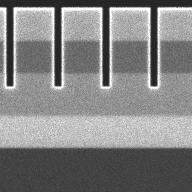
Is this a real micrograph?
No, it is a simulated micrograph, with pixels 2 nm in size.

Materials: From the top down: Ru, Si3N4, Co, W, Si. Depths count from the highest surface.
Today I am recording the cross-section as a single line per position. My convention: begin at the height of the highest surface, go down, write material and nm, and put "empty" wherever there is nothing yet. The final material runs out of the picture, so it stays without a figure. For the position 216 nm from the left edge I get empty 158, Co 58, W 64, Si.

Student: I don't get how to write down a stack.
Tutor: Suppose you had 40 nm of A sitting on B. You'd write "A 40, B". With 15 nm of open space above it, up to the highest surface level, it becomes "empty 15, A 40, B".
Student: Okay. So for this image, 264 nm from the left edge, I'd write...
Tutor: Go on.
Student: Ru 66, Si3N4 64, Co 86, W 64, Si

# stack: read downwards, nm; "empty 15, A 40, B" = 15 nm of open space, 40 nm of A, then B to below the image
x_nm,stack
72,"Ru 66, Si3N4 64, Co 86, W 64, Si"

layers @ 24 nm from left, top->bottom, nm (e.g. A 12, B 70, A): empty 158, Co 58, W 64, Si